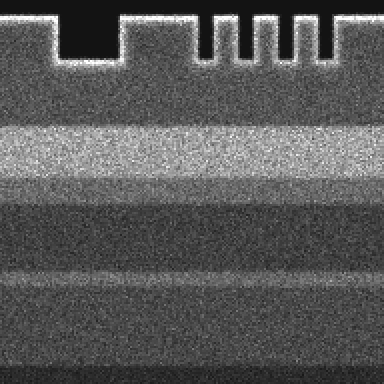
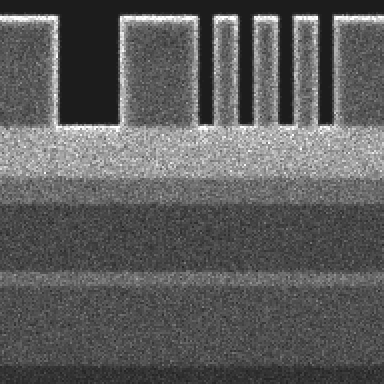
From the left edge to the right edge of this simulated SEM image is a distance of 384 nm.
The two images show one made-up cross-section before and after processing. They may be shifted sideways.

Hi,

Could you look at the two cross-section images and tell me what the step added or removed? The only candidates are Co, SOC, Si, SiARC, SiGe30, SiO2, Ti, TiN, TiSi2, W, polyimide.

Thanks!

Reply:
removed SOC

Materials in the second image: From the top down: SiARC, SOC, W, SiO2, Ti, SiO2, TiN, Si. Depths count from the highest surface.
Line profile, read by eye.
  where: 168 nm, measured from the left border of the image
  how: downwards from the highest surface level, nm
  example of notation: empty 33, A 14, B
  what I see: SiARC 44, SOC 66, W 52, SiO2 26, Ti 68, SiO2 14, TiN 80, Si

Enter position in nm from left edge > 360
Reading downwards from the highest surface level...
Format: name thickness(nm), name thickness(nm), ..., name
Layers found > SiARC 44, SOC 66, W 52, SiO2 26, Ti 68, SiO2 14, TiN 80, Si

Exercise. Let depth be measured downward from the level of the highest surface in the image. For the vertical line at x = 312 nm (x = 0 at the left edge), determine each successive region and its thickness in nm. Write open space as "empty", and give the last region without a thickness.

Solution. SiARC 44, SOC 66, W 52, SiO2 26, Ti 68, SiO2 14, TiN 80, Si